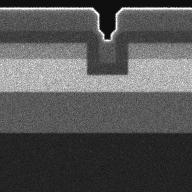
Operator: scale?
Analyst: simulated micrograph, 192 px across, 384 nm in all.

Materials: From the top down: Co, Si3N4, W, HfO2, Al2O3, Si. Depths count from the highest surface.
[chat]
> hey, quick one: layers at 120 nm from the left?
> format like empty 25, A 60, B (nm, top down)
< Co 46, Si3N4 24, W 32, HfO2 66, Al2O3 82, Si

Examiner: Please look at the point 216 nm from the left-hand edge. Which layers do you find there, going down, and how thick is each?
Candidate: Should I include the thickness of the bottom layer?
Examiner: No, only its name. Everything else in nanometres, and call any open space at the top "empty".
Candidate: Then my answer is empty 64, Co 46, Si3N4 24, HfO2 34, Al2O3 82, Si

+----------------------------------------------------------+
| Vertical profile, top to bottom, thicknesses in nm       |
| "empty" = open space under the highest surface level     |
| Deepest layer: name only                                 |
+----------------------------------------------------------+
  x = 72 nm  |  Co 46, Si3N4 24, W 32, HfO2 66, Al2O3 82, Si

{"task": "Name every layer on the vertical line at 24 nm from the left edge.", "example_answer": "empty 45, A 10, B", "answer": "Co 46, Si3N4 24, W 32, HfO2 66, Al2O3 82, Si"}